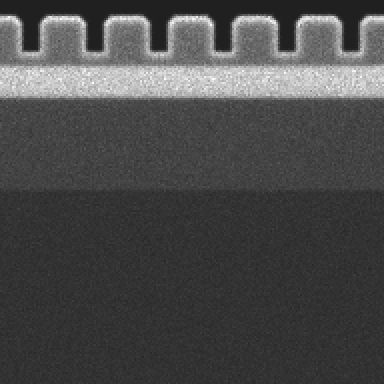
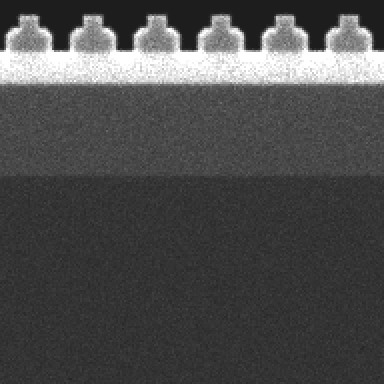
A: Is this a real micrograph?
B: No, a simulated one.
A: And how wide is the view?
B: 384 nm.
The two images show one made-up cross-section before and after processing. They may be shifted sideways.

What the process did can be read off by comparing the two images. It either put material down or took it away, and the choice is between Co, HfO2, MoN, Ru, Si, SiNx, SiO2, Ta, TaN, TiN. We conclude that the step removed SiO2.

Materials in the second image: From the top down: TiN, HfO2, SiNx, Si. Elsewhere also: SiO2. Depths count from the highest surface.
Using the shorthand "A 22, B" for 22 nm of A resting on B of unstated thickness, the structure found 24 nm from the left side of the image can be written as TiN 36, HfO2 32, SiNx 92, Si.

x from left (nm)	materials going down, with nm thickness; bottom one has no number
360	empty 12, SiO2 24, HfO2 32, SiNx 92, Si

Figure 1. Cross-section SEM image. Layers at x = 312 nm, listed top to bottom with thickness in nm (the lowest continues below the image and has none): empty 36, HfO2 32, SiNx 92, Si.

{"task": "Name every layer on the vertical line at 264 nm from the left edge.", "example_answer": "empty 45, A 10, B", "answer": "empty 16, SiO2 20, HfO2 32, SiNx 92, Si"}